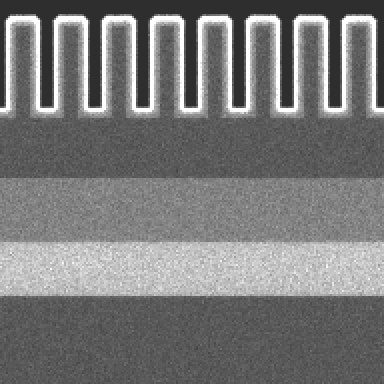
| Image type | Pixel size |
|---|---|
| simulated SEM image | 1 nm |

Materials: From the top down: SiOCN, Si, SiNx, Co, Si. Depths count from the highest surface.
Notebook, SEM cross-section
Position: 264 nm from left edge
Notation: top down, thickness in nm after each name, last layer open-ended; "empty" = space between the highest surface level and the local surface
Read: SiOCN 10, Si 152, SiNx 64, Co 54, Si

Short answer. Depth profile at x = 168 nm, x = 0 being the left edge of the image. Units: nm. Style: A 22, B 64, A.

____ SiOCN 10, Si 152, SiNx 64, Co 54, Si